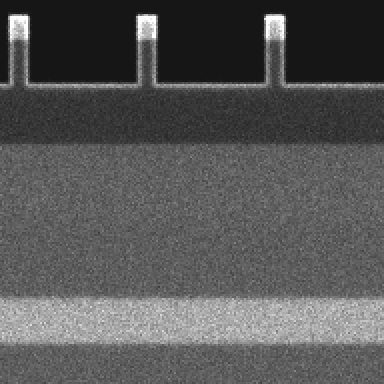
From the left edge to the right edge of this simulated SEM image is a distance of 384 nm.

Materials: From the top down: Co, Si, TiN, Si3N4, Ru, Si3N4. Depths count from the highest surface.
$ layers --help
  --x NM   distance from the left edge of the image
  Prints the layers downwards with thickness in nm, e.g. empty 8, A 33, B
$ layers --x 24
Co 24, Si 104, TiN 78, Si3N4 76, Ru 46, Si3N4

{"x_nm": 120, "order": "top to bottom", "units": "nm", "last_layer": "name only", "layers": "empty 68, Si 60, TiN 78, Si3N4 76, Ru 46, Si3N4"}